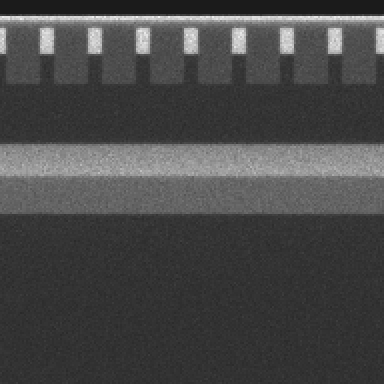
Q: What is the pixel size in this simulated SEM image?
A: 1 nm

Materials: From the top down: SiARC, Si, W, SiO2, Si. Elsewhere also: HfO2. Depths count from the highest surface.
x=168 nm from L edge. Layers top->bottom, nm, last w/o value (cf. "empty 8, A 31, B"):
SiARC 68, Si 60, W 32, SiO2 38, Si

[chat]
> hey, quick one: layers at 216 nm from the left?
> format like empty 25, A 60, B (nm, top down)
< SiARC 68, Si 60, W 32, SiO2 38, Si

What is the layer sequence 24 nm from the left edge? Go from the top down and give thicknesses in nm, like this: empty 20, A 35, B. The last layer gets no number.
SiARC 68, Si 60, W 32, SiO2 38, Si